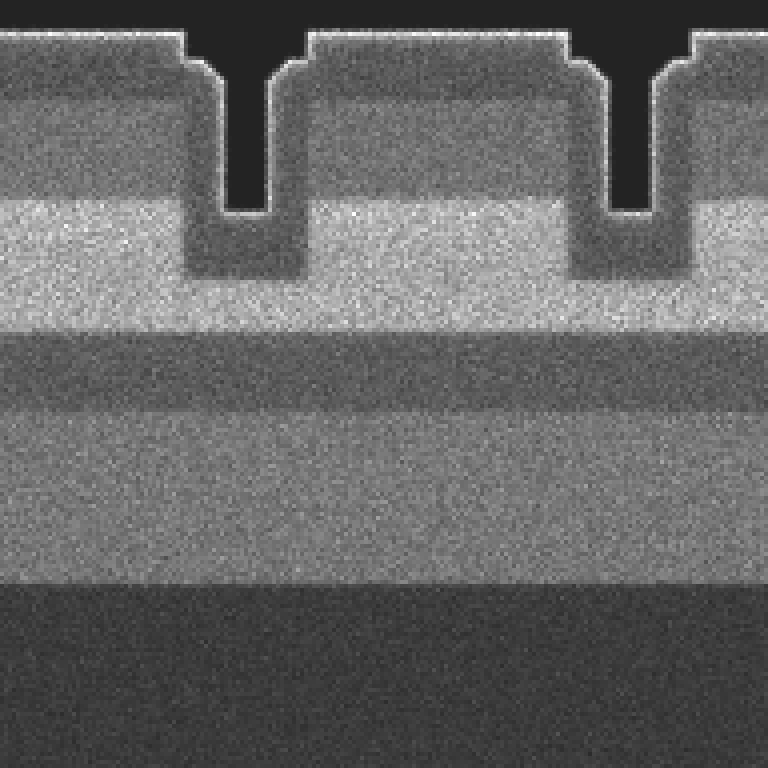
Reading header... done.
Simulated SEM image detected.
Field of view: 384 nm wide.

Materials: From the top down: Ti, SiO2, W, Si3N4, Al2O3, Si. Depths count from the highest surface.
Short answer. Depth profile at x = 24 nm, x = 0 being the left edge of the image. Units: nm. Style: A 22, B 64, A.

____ Ti 34, SiO2 50, W 66, Si3N4 40, Al2O3 86, Si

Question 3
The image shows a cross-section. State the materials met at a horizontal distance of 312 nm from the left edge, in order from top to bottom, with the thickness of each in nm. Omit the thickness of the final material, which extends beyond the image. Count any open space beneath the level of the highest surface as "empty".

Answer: empty 90, Ti 34, W 26, Si3N4 40, Al2O3 86, Si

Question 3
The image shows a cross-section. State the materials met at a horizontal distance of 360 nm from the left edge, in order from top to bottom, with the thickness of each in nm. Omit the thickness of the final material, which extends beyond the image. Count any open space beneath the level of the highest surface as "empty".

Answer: Ti 34, SiO2 50, W 66, Si3N4 40, Al2O3 86, Si